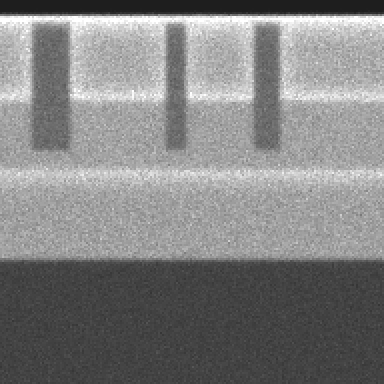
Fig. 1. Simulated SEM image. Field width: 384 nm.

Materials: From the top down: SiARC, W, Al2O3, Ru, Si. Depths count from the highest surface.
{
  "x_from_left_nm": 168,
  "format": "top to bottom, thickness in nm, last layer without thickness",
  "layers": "SiARC 134, Al2O3 20, Ru 90, Si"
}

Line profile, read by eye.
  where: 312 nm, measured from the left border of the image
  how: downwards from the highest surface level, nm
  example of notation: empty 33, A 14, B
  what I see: SiARC 6, W 78, Al2O3 70, Ru 90, Si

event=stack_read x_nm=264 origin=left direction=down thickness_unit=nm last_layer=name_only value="SiARC 134, Al2O3 20, Ru 90, Si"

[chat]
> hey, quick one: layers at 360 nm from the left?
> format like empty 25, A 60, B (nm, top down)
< SiARC 6, W 78, Al2O3 70, Ru 90, Si